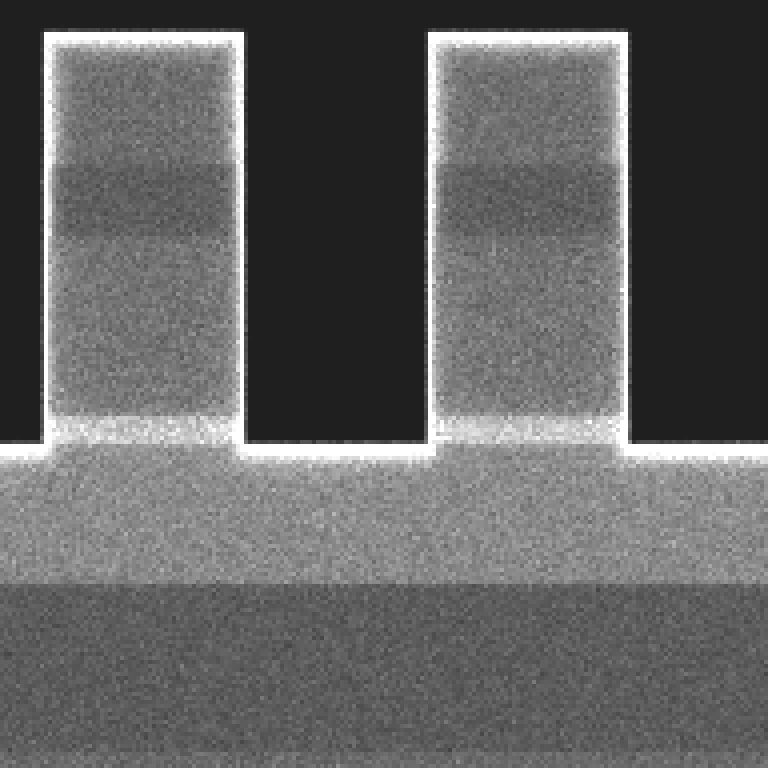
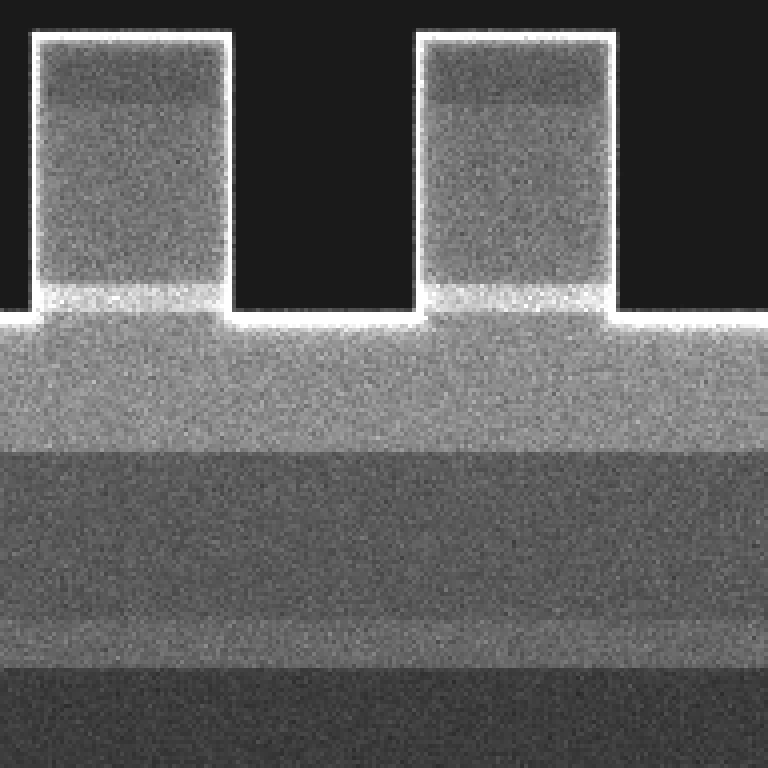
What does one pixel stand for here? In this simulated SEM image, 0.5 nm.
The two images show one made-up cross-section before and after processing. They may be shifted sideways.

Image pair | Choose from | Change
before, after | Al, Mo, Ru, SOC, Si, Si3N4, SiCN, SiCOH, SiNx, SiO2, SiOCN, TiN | SOC (removed)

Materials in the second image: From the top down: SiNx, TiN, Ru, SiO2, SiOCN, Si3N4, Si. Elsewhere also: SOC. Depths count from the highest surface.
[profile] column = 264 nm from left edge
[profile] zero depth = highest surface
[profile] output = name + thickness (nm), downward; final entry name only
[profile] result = SiNx 36, TiN 90, Ru 14, SiO2 70, SiOCN 84, Si3N4 24, Si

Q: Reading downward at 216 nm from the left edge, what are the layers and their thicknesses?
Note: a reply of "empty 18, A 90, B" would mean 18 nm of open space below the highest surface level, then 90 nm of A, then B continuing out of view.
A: SiNx 36, TiN 90, Ru 14, SiO2 70, SiOCN 84, Si3N4 24, Si